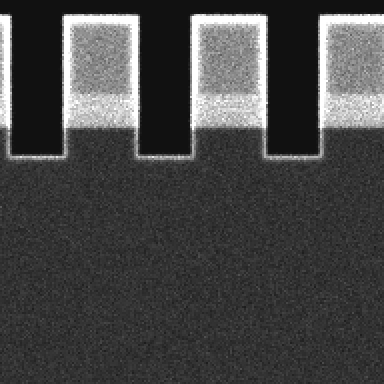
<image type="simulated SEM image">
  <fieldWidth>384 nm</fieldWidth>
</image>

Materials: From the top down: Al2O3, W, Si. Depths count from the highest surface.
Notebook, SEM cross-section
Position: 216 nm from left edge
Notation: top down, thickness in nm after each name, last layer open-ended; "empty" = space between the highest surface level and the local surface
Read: Al2O3 78, W 34, Si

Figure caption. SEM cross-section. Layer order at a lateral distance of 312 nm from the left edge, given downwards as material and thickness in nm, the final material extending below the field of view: empty 140, Si